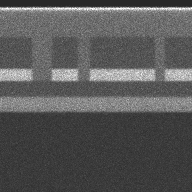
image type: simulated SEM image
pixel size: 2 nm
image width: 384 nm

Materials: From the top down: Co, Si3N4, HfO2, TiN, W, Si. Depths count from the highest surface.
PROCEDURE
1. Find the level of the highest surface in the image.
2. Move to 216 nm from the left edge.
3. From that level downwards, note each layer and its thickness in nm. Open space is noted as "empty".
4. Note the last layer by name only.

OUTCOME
Co 58, Si3N4 64, HfO2 24, TiN 32, W 30, Si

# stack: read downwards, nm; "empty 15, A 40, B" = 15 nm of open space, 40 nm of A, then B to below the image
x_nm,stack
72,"Co 146, TiN 32, W 30, Si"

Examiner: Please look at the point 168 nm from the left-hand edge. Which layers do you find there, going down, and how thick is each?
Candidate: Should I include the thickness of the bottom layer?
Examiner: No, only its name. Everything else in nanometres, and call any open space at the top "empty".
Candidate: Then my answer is Co 146, TiN 32, W 30, Si